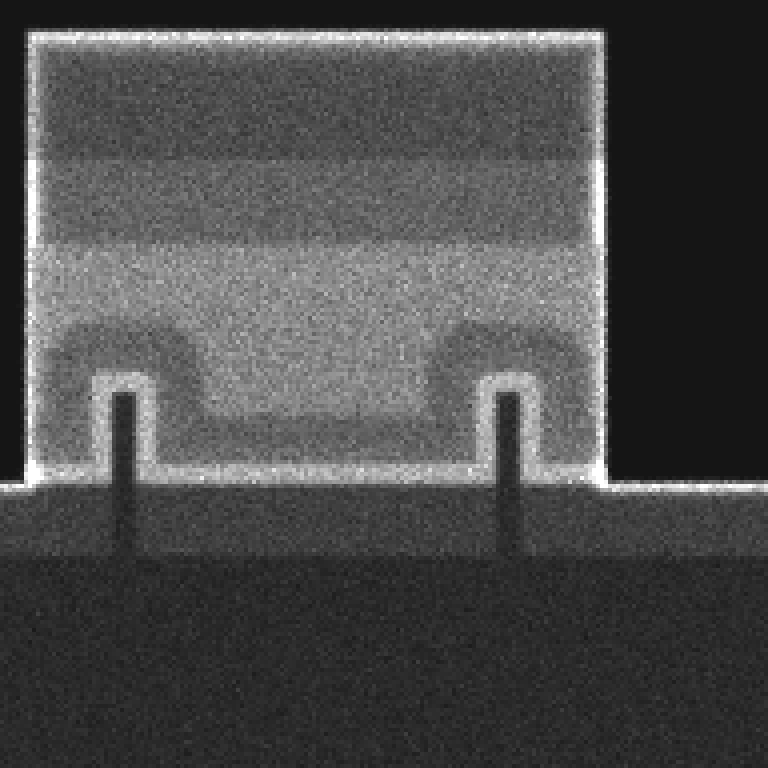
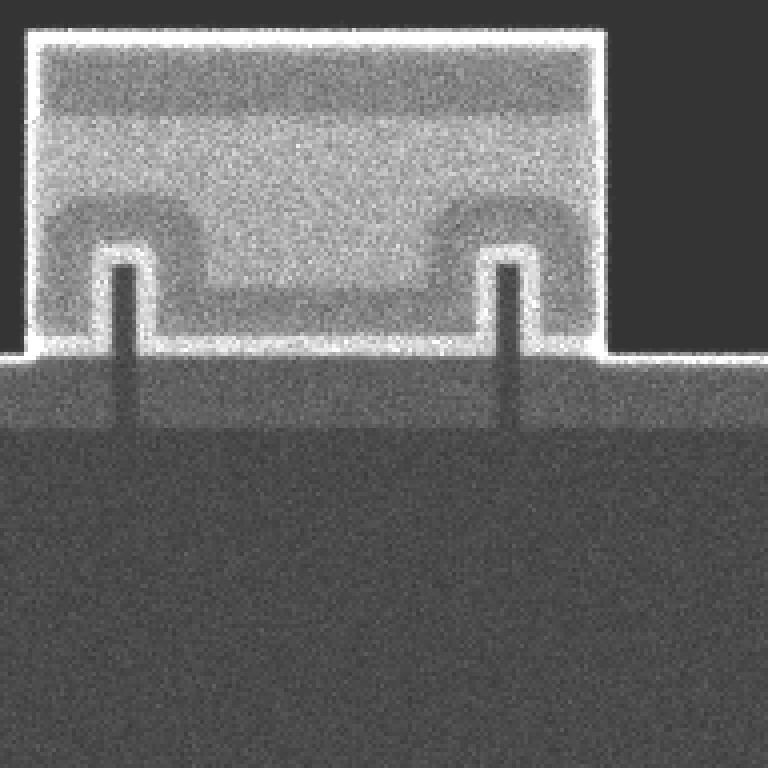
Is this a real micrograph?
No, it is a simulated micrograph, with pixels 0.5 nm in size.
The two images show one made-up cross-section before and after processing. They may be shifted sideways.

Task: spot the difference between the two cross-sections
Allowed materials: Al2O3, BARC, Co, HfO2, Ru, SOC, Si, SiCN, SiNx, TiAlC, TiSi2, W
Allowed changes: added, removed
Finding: removed SOC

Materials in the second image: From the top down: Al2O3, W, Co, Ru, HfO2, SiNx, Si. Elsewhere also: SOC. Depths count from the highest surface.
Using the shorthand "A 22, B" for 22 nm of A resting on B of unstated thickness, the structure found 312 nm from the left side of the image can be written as empty 162, SiNx 36, Si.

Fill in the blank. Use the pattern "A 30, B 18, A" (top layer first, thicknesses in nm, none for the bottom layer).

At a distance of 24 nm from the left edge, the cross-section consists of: Al2O3 42, W 52, Co 48, Ru 10, HfO2 10, SiNx 36, Si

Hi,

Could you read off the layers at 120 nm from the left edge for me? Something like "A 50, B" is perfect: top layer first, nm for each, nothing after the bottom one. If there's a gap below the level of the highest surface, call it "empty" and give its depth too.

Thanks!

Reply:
Al2O3 42, W 86, Co 14, Ru 10, HfO2 10, SiNx 36, Si